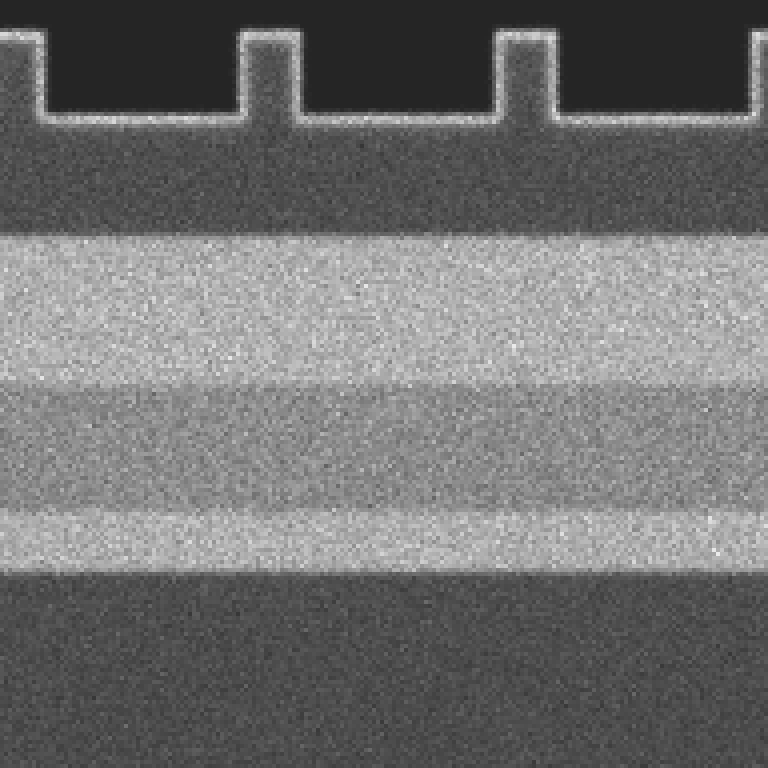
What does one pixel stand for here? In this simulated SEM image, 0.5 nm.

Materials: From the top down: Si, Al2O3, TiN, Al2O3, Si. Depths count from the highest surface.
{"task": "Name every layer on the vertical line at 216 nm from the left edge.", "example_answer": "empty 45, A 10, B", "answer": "empty 42, Si 60, Al2O3 74, TiN 64, Al2O3 30, Si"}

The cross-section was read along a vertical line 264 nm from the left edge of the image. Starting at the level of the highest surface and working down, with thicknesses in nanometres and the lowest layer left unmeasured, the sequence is Si 102, Al2O3 74, TiN 64, Al2O3 30, Si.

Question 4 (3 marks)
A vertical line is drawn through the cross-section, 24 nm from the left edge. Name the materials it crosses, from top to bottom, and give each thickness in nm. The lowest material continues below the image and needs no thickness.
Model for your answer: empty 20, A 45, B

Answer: empty 42, Si 60, Al2O3 74, TiN 64, Al2O3 30, Si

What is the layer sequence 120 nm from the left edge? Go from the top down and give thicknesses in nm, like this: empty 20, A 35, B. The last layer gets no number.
Si 102, Al2O3 74, TiN 64, Al2O3 30, Si